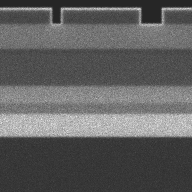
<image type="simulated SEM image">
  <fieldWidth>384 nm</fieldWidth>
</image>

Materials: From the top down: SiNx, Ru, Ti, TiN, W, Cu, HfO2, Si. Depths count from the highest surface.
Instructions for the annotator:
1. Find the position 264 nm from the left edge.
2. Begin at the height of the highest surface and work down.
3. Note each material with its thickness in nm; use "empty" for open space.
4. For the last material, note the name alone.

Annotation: SiNx 32, Ru 50, Ti 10, TiN 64, W 34, Cu 22, HfO2 46, Si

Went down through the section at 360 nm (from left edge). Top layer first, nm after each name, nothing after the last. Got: SiNx 32, Ru 50, Ti 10, TiN 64, W 34, Cu 22, HfO2 46, Si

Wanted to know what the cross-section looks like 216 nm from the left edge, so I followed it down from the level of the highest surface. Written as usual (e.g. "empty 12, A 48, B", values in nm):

SiNx 32, Ru 50, Ti 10, TiN 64, W 34, Cu 22, HfO2 46, Si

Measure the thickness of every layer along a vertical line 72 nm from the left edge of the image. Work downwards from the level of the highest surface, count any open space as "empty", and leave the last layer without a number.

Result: SiNx 32, Ru 50, Ti 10, TiN 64, W 34, Cu 22, HfO2 46, Si